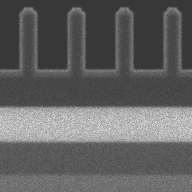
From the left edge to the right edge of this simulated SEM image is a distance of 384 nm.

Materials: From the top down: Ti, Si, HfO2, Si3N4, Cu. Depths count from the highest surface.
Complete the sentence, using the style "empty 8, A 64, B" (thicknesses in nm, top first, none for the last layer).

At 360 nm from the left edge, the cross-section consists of empty 10, Ti 128, Si 60, HfO2 70, Si3N4 66, Cu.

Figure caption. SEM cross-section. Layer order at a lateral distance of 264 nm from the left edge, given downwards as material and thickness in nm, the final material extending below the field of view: empty 10, Ti 128, Si 60, HfO2 70, Si3N4 66, Cu